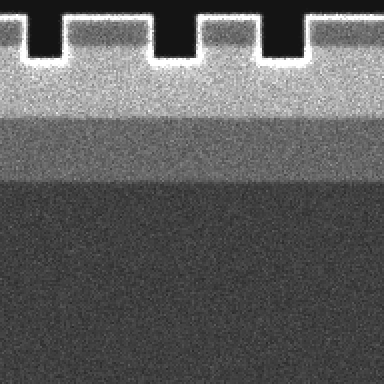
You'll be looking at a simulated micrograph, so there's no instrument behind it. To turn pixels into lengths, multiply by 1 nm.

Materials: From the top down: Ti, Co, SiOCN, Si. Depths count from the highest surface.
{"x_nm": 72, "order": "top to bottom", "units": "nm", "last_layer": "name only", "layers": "Ti 30, Co 72, SiOCN 64, Si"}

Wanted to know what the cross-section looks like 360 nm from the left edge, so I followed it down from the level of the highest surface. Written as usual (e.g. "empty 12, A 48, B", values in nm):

Ti 30, Co 72, SiOCN 64, Si